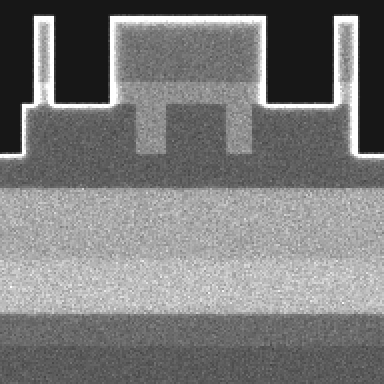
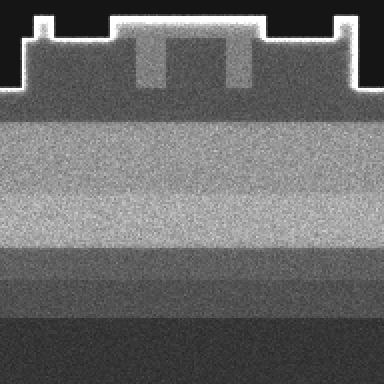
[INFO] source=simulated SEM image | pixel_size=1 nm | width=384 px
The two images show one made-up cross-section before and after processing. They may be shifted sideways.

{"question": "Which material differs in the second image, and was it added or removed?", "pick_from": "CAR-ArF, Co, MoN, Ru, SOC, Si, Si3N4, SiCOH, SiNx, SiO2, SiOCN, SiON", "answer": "SOC, removed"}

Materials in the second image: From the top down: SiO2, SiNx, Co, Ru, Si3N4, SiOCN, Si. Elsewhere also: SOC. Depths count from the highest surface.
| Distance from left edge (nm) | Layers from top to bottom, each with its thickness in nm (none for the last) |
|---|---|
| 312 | empty 22, SiNx 84, Co 72, Ru 54, Si3N4 32, SiOCN 38, Si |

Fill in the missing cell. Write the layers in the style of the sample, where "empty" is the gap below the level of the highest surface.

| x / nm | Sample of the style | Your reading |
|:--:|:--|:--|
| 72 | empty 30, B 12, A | empty 22, SiNx 84, Co 72, Ru 54, Si3N4 32, SiOCN 38, Si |